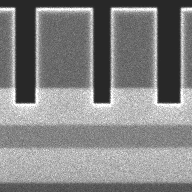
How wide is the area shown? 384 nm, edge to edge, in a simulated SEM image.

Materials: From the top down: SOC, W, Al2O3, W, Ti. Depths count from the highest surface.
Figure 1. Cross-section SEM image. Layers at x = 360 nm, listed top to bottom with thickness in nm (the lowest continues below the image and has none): empty 192, W 42, Al2O3 46, W 70, Ti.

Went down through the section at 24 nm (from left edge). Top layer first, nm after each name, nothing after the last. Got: SOC 160, W 74, Al2O3 46, W 70, Ti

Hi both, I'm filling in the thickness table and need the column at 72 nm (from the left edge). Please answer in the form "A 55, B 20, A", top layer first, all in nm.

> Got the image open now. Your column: SOC 160, W 74, Al2O3 46, W 70, Ti